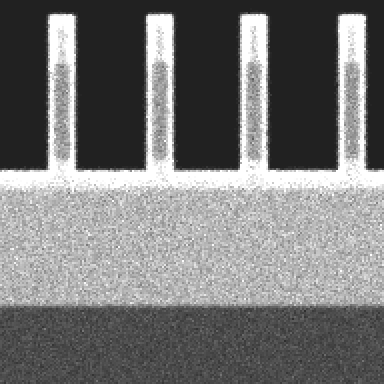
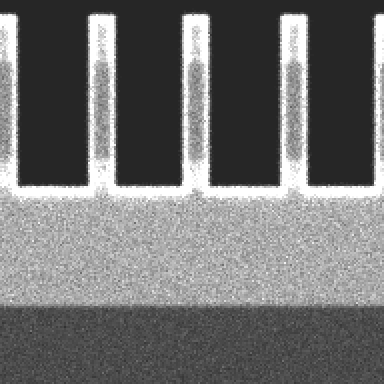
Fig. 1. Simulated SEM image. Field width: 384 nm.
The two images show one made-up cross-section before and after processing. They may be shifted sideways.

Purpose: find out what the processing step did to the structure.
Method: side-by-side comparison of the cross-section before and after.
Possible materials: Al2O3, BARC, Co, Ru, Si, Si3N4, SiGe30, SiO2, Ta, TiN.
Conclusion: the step removed Ru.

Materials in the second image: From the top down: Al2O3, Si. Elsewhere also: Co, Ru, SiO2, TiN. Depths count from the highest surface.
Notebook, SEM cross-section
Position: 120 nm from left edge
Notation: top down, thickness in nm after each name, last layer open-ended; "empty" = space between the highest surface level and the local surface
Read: empty 172, Al2O3 118, Si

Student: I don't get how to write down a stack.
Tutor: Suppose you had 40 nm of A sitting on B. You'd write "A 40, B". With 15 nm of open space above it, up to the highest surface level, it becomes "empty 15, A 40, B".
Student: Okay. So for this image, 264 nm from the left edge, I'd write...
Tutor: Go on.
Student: empty 172, Al2O3 118, Si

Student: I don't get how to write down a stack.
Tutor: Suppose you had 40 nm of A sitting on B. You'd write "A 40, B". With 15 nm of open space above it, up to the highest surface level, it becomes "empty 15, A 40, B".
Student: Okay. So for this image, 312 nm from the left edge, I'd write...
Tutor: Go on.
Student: empty 172, Al2O3 118, Si